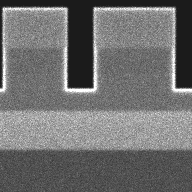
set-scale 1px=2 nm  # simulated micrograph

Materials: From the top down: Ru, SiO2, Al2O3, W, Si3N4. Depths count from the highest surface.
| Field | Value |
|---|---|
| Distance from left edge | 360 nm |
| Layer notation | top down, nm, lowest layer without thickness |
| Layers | empty 162, Al2O3 44, W 78, Si3N4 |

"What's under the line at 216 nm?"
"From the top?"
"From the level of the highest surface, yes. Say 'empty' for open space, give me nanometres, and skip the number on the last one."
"Ru 80, SiO2 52, Al2O3 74, W 78, Si3N4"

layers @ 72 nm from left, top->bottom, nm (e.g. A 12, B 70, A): Ru 80, SiO2 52, Al2O3 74, W 78, Si3N4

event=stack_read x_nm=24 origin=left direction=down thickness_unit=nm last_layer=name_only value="Ru 80, SiO2 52, Al2O3 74, W 78, Si3N4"